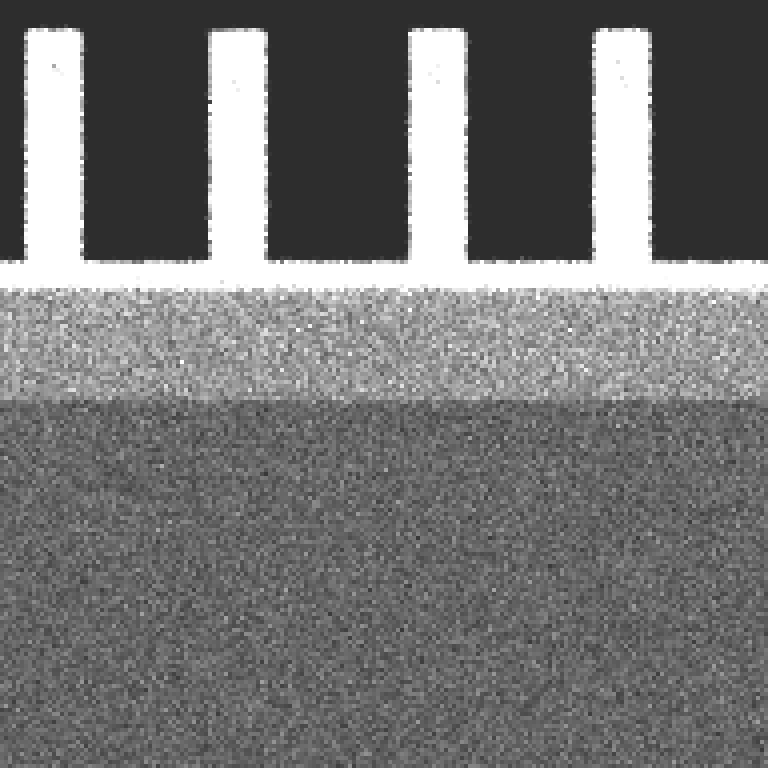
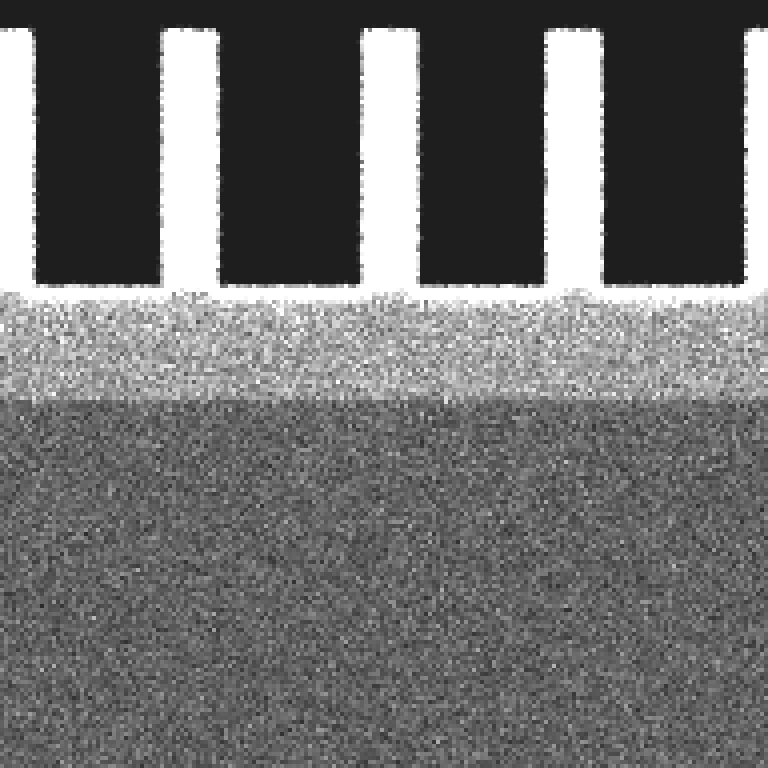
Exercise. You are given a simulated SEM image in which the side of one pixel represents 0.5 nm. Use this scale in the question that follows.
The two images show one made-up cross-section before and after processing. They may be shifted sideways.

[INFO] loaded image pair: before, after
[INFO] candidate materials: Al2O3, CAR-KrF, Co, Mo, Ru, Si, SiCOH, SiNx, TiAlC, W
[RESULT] removed Ru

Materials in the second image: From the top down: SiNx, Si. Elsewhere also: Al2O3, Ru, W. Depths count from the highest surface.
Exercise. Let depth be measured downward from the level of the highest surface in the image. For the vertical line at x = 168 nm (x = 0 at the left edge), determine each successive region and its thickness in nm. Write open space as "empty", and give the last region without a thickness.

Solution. empty 128, SiNx 56, Si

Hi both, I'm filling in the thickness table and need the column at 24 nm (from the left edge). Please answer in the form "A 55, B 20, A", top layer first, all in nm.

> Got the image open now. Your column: empty 128, SiNx 56, Si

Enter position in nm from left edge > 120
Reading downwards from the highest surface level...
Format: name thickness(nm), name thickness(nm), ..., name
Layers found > empty 128, SiNx 56, Si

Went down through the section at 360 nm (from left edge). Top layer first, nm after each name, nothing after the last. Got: empty 128, SiNx 56, Si